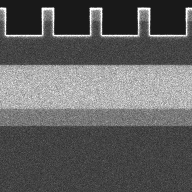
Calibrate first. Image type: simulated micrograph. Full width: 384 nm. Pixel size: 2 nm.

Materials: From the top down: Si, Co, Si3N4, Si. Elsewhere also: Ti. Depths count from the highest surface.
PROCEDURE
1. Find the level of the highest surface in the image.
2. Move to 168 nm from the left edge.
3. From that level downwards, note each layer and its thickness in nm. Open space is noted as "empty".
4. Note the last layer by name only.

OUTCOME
empty 54, Si 60, Co 88, Si3N4 34, Si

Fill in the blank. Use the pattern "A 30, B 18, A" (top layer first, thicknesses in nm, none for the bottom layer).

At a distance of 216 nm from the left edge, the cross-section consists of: empty 54, Si 60, Co 88, Si3N4 34, Si